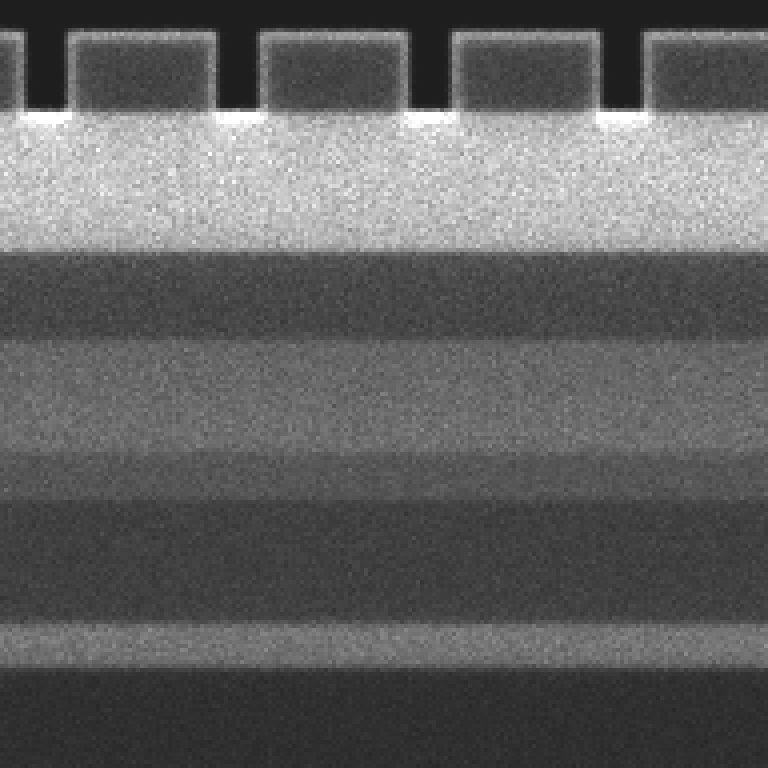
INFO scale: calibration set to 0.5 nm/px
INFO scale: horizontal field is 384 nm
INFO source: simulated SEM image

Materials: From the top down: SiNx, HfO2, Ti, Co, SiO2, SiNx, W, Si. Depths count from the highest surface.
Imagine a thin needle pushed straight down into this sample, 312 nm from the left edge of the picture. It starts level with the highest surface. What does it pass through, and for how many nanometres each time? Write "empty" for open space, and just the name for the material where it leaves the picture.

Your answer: empty 40, HfO2 70, Ti 44, Co 56, SiO2 24, SiNx 62, W 22, Si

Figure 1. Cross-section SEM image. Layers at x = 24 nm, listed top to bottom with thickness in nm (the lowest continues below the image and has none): empty 40, HfO2 70, Ti 44, Co 56, SiO2 24, SiNx 62, W 22, Si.